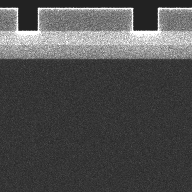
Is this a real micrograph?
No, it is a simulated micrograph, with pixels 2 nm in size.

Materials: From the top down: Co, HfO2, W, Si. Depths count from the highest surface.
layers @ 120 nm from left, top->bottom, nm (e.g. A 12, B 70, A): Co 46, HfO2 28, W 28, Si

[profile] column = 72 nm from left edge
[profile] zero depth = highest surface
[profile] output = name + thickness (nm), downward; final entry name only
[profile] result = empty 46, HfO2 28, W 28, Si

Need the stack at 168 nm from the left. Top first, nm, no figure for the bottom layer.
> Co 46, HfO2 28, W 28, Si